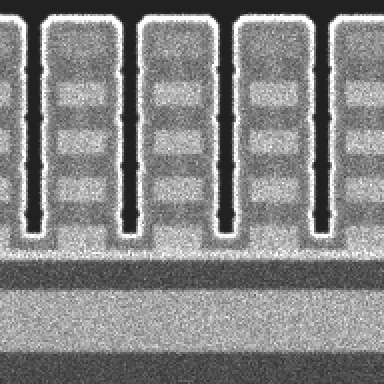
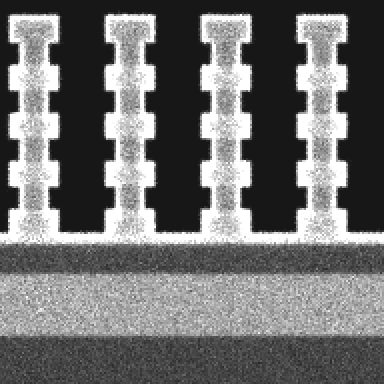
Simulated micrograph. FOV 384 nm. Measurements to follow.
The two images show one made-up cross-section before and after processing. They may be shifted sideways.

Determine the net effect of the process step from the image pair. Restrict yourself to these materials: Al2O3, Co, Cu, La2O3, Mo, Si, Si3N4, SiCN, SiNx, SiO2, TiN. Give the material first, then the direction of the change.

SiNx: removed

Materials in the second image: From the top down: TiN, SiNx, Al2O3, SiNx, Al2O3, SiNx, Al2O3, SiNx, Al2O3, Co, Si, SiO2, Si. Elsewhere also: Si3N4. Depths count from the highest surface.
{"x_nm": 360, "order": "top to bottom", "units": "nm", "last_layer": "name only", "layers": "empty 218, Co 10, Si 30, SiO2 62, Si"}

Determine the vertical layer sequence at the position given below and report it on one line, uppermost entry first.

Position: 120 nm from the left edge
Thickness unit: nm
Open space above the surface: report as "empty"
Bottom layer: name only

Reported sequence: TiN 26, SiNx 24, Al2O3 24, SiNx 24, Al2O3 24, SiNx 24, Al2O3 24, SiNx 24, Al2O3 24, Co 10, Si 30, SiO2 62, Si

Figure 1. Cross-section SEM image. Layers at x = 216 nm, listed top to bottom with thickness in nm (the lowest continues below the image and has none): TiN 26, SiNx 24, Al2O3 24, SiNx 24, Al2O3 24, SiNx 24, Al2O3 24, SiNx 24, Al2O3 24, Co 10, Si 30, SiO2 62, Si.